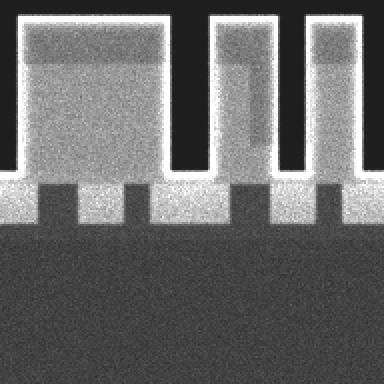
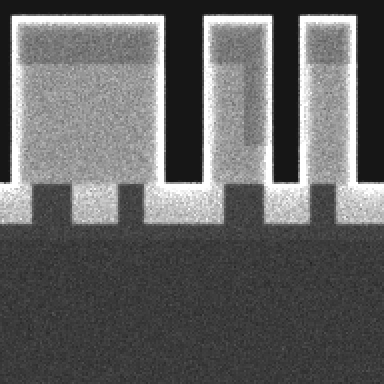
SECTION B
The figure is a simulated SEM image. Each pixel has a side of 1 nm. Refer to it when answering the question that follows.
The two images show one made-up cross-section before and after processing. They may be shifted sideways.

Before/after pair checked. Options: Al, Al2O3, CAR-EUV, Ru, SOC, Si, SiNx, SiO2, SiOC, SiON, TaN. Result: removed Al2O3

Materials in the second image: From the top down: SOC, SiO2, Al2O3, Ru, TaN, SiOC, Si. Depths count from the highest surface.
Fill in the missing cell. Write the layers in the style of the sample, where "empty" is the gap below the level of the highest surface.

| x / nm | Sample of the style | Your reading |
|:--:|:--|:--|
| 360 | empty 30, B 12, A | empty 168, Ru 34, TaN 6, SiOC 16, Si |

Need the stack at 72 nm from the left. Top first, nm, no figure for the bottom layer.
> SOC 48, SiO2 108, Al2O3 12, TaN 40, SiOC 16, Si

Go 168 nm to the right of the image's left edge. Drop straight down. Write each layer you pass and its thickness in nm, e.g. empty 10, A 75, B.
empty 168, Ru 34, TaN 6, SiOC 16, Si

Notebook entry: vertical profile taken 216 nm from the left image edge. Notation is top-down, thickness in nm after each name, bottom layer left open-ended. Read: SOC 48, SiO2 108, Al2O3 12, Ru 34, TaN 6, SiOC 16, Si